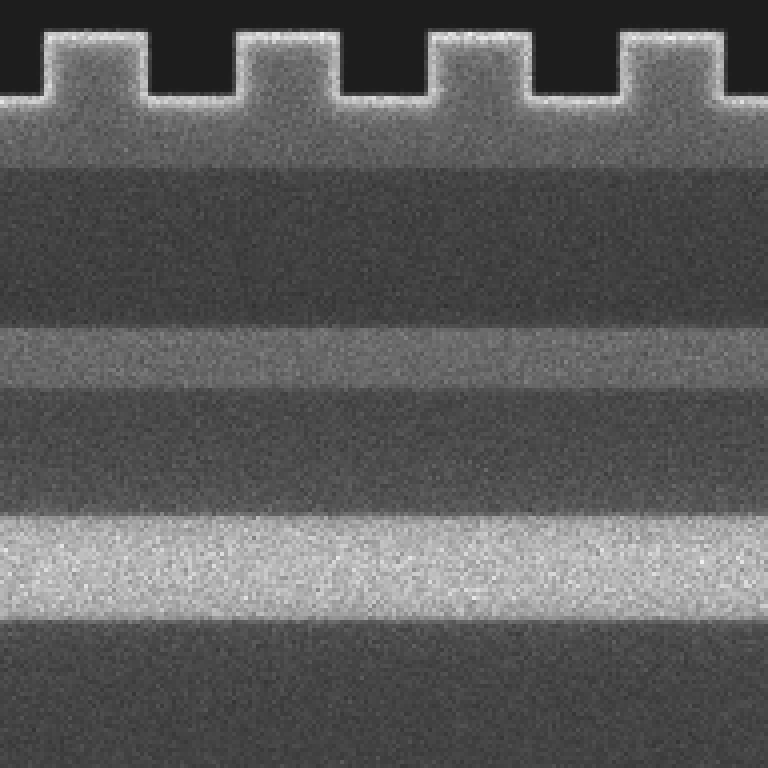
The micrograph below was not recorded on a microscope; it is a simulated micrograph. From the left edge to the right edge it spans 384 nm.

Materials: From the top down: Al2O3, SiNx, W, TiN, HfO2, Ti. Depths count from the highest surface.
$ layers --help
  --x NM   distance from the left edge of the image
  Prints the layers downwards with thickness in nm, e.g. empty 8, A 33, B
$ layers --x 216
Al2O3 68, SiNx 80, W 30, TiN 64, HfO2 52, Ti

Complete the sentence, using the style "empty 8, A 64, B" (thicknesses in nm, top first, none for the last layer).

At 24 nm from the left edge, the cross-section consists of Al2O3 68, SiNx 80, W 30, TiN 64, HfO2 52, Ti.